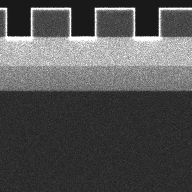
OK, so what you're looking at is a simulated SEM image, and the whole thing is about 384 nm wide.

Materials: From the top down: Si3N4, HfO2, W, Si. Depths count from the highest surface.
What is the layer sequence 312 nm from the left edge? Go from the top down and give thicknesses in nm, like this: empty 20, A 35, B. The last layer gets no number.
empty 58, HfO2 58, W 50, Si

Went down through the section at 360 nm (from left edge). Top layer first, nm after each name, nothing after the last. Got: Si3N4 58, HfO2 58, W 50, Si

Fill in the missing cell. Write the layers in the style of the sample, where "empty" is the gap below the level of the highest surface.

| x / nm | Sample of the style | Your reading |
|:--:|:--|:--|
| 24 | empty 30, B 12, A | empty 58, HfO2 58, W 50, Si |